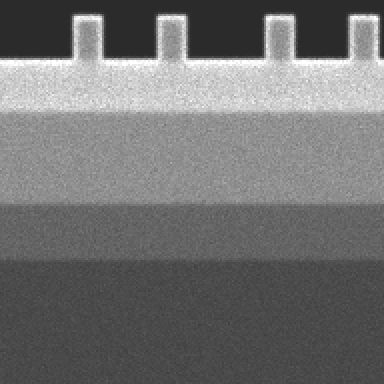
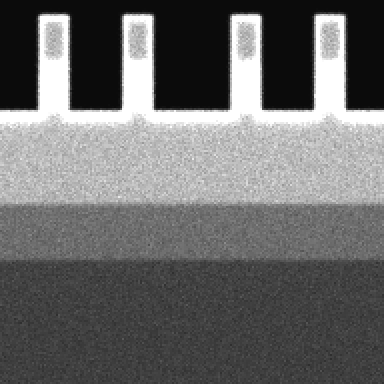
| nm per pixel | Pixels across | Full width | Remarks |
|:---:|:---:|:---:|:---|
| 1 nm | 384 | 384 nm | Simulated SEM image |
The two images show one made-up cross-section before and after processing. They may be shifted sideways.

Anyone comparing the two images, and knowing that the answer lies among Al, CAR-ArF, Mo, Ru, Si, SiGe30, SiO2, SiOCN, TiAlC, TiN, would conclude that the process removed Ru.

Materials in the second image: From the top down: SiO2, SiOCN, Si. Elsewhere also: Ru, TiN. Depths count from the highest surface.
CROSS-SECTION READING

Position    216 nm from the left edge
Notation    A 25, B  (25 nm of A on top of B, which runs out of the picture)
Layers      empty 96, SiO2 92, SiOCN 56, Si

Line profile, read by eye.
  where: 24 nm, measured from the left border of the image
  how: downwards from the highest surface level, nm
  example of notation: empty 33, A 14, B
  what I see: empty 96, SiO2 92, SiOCN 56, Si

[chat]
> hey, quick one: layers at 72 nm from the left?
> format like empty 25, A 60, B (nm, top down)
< empty 96, SiO2 92, SiOCN 56, Si